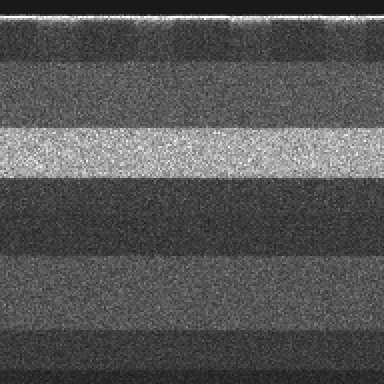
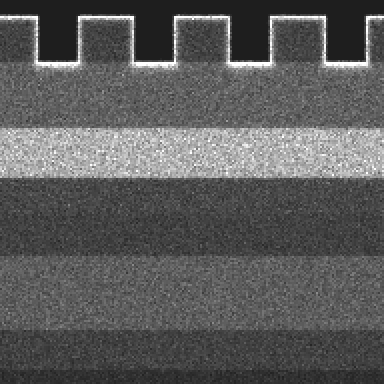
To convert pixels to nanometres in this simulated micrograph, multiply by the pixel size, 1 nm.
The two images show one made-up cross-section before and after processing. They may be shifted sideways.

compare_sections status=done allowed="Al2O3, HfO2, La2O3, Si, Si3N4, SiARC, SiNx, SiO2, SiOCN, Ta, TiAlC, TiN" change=removed material="SiARC"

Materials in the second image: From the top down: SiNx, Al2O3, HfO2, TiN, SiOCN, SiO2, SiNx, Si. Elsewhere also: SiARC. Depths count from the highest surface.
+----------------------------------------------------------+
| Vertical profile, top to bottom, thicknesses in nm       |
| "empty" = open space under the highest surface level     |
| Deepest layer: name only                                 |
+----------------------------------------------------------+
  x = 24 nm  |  SiNx 46, Al2O3 66, HfO2 50, TiN 36, SiOCN 42, SiO2 74, SiNx 40, Si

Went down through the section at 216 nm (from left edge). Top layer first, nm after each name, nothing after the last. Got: SiNx 46, Al2O3 66, HfO2 50, TiN 36, SiOCN 42, SiO2 74, SiNx 40, Si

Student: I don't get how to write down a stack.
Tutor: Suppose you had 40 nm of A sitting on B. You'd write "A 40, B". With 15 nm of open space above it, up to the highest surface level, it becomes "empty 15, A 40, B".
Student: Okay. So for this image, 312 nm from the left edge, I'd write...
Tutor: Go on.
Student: SiNx 46, Al2O3 66, HfO2 50, TiN 36, SiOCN 42, SiO2 74, SiNx 40, Si